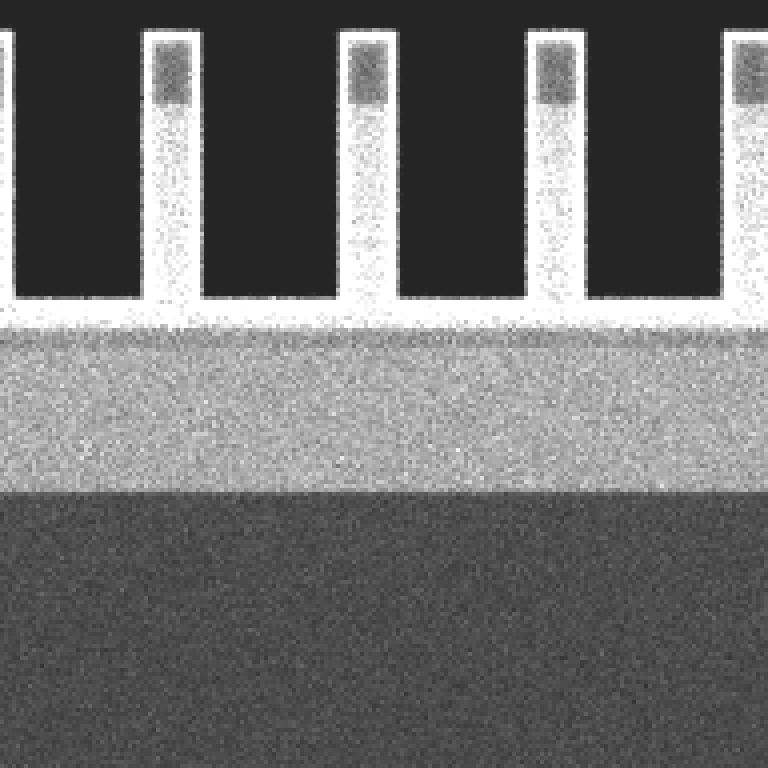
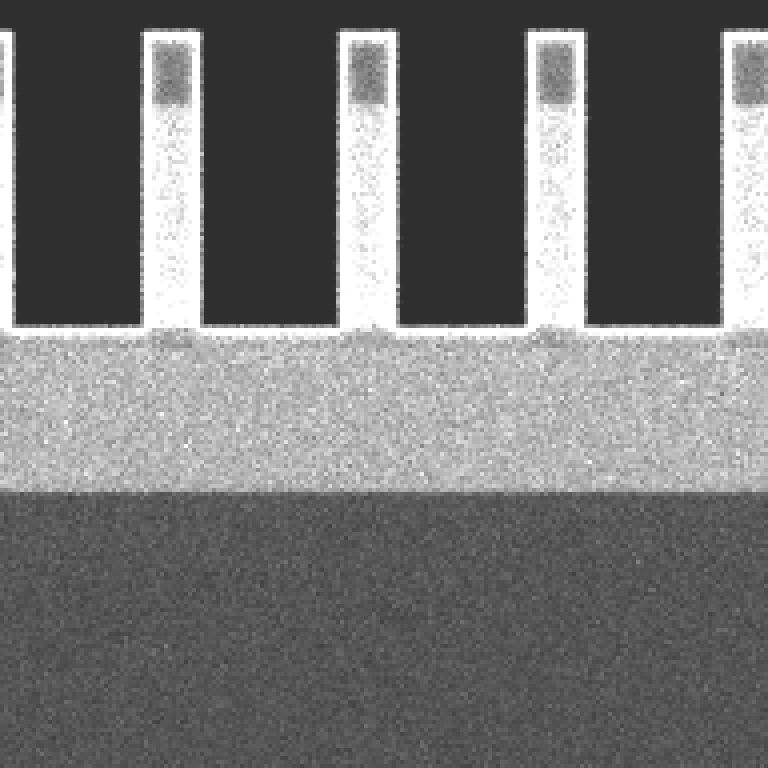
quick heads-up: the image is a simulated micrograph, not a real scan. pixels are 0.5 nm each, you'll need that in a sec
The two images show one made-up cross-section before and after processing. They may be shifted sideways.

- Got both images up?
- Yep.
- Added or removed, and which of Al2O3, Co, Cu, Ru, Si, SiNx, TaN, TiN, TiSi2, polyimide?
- removed, Ru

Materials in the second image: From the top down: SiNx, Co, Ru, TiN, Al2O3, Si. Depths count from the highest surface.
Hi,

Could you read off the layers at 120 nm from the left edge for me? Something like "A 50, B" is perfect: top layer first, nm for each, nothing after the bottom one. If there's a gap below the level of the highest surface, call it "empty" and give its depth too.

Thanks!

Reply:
empty 148, TiN 10, Al2O3 72, Si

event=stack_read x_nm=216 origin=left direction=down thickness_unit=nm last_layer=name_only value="empty 148, TiN 10, Al2O3 72, Si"